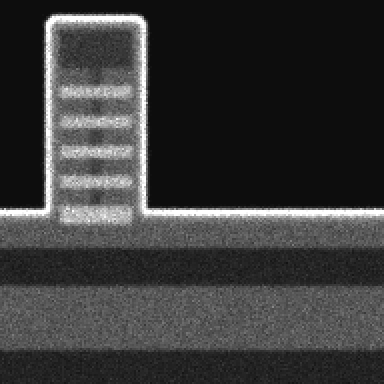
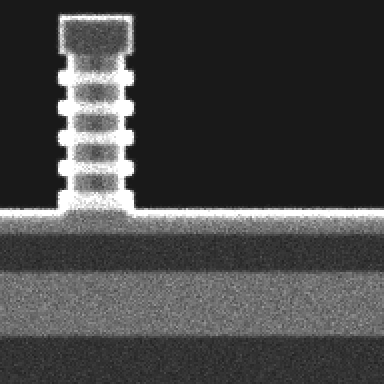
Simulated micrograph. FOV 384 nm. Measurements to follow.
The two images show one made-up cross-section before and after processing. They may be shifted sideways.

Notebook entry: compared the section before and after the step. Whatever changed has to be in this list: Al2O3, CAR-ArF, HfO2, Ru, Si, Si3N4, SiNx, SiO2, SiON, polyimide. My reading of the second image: Al2O3 removed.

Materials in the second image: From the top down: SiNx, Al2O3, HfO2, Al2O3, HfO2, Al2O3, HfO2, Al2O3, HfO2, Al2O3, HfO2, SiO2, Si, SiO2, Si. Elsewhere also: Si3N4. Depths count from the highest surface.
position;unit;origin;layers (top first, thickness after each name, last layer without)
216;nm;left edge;empty 194, SiO2 24, Si 38, SiO2 64, Si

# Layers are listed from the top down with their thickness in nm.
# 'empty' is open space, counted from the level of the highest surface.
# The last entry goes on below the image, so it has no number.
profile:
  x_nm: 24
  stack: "empty 194, SiO2 24, Si 38, SiO2 64, Si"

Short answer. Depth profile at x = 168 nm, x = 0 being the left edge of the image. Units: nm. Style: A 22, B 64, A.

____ empty 194, SiO2 24, Si 38, SiO2 64, Si